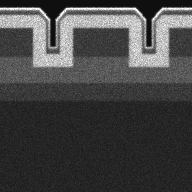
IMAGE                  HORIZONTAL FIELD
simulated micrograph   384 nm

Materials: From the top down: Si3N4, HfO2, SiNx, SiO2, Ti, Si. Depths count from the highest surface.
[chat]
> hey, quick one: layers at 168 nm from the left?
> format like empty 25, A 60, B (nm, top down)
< Si3N4 14, HfO2 26, SiNx 58, SiO2 52, Ti 36, Si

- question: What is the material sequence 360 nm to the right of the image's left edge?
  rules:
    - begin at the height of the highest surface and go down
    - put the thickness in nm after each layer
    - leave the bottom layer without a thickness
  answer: Si3N4 14, HfO2 26, SiNx 58, SiO2 52, Ti 36, Si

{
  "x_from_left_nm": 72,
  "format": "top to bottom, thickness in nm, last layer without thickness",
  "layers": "Si3N4 14, HfO2 104, SiO2 32, Ti 36, Si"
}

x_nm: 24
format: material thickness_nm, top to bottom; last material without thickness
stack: Si3N4 14, HfO2 26, SiNx 58, SiO2 52, Ti 36, Si